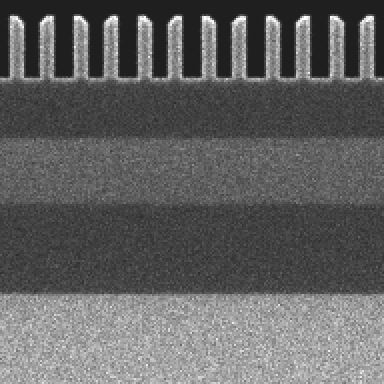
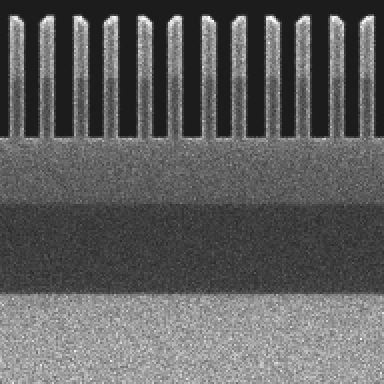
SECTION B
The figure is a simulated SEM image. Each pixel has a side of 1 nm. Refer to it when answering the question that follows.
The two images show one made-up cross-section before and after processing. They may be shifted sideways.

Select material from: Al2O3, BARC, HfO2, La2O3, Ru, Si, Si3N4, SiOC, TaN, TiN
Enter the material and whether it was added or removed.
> Si3N4 / removed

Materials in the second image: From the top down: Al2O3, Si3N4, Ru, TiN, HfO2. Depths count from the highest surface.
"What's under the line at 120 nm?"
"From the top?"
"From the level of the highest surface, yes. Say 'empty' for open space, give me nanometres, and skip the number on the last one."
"empty 122, Ru 66, TiN 90, HfO2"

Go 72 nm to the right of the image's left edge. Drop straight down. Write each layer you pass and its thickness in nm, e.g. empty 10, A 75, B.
empty 122, Ru 66, TiN 90, HfO2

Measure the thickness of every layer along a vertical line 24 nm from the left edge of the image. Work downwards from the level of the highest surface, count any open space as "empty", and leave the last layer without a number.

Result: empty 122, Ru 66, TiN 90, HfO2